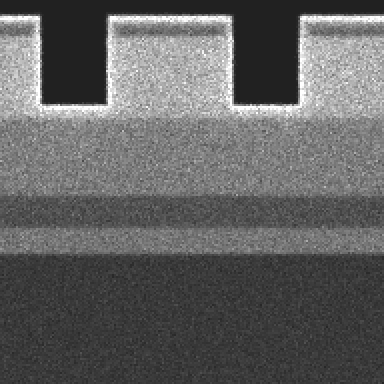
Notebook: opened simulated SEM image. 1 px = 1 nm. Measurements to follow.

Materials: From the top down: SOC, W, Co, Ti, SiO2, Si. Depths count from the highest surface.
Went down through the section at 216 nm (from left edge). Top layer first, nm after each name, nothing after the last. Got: SOC 20, W 82, Co 78, Ti 32, SiO2 26, Si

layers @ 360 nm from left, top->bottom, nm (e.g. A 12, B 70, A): SOC 20, W 82, Co 78, Ti 32, SiO2 26, Si